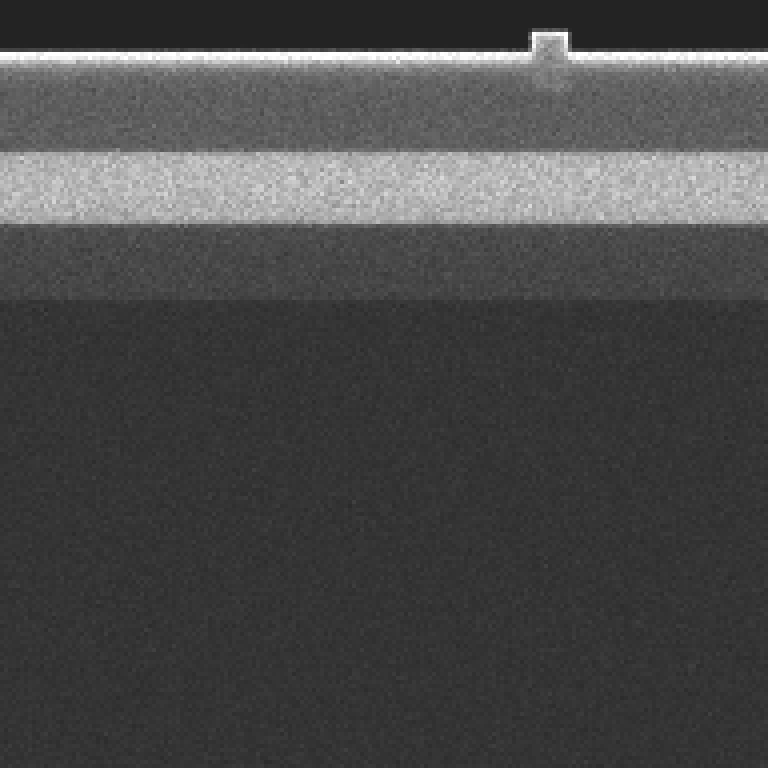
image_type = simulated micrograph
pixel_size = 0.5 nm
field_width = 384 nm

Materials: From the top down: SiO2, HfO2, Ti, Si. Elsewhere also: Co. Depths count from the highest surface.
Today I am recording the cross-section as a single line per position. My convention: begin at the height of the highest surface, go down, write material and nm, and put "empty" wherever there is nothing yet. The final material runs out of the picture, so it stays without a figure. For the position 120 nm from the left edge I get empty 10, SiO2 50, HfO2 36, Ti 38, Si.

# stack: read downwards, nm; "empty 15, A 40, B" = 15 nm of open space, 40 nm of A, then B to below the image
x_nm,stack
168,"empty 10, SiO2 50, HfO2 36, Ti 38, Si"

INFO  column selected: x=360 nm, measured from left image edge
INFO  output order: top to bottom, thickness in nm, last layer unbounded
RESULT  empty 10, SiO2 50, HfO2 36, Ti 38, Si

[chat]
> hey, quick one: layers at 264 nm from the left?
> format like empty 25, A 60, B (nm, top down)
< empty 10, SiO2 50, HfO2 36, Ti 38, Si